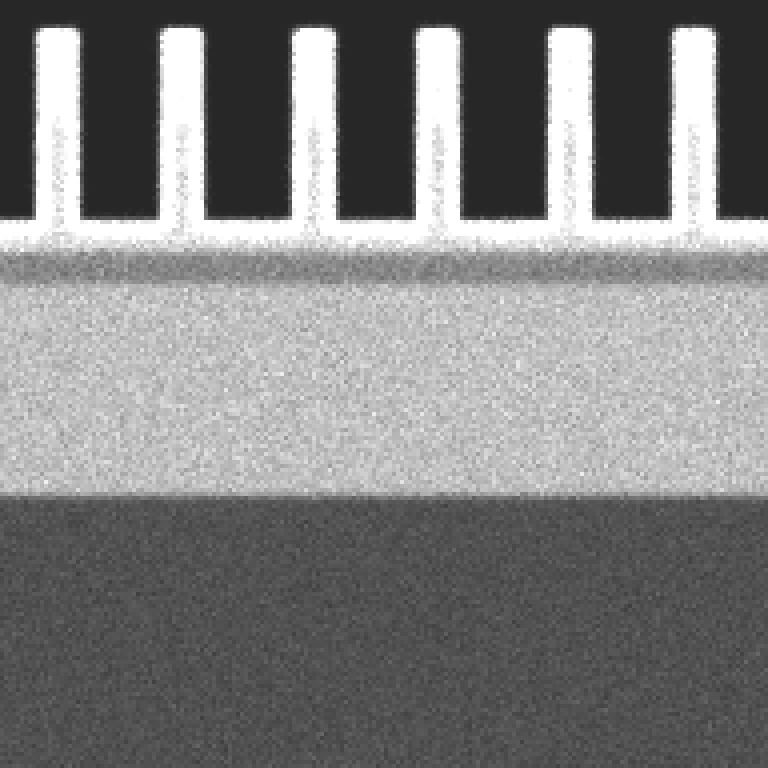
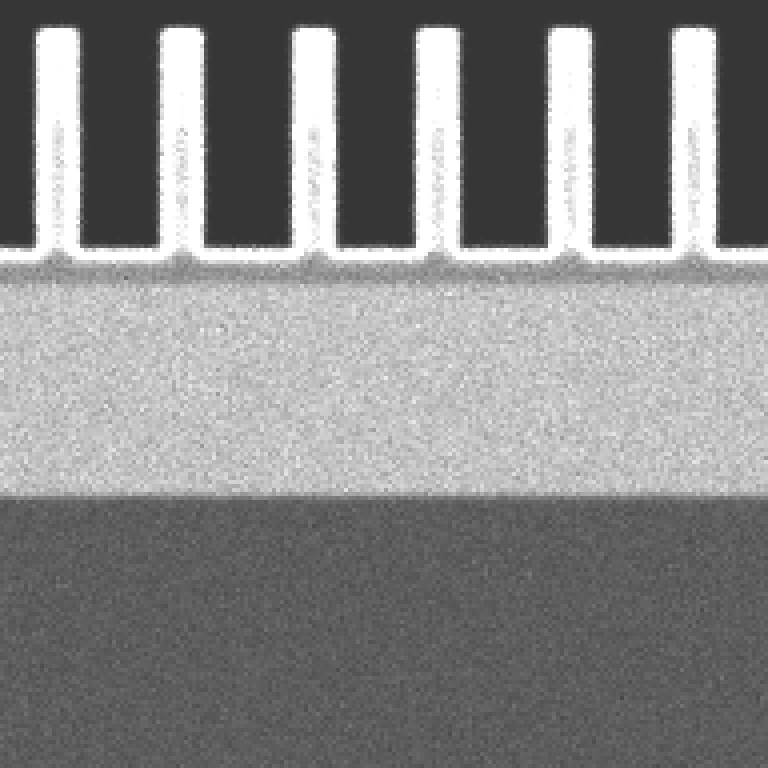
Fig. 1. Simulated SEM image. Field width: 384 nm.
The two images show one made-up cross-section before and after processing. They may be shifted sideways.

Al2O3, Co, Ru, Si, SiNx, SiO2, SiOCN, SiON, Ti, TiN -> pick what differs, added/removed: Ru removed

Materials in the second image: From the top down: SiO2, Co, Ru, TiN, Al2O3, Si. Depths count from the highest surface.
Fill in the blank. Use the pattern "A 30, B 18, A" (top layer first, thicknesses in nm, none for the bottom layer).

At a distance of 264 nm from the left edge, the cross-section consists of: empty 110, TiN 16, Al2O3 106, Si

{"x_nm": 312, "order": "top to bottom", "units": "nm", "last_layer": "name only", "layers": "empty 110, TiN 16, Al2O3 106, Si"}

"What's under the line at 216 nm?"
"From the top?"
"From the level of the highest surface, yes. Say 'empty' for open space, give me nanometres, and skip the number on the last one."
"SiO2 44, Co 52, Ru 14, TiN 16, Al2O3 106, Si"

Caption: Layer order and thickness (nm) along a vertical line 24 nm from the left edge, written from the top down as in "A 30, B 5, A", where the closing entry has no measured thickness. SiO2 44, Co 52, Ru 14, TiN 16, Al2O3 106, Si